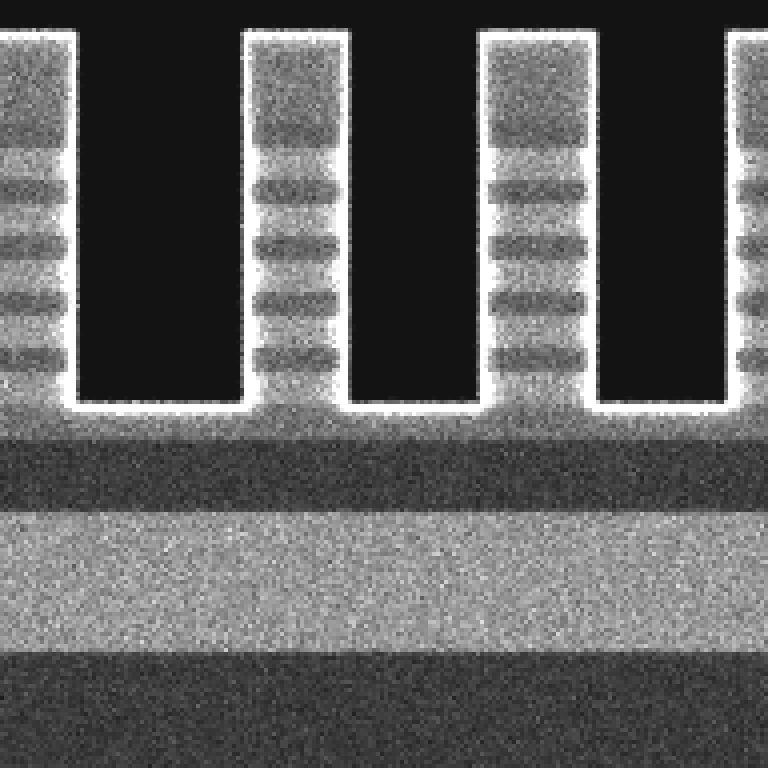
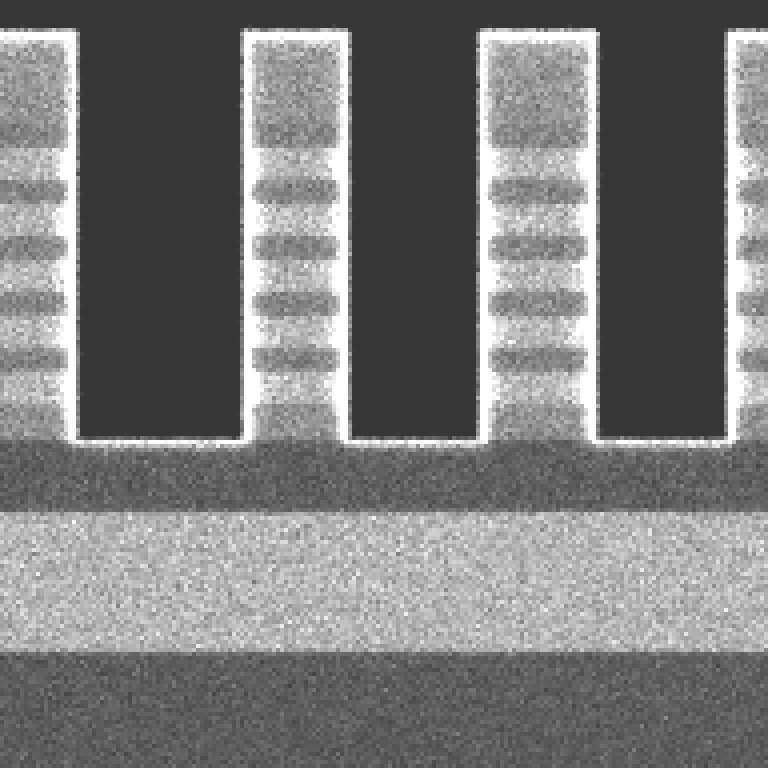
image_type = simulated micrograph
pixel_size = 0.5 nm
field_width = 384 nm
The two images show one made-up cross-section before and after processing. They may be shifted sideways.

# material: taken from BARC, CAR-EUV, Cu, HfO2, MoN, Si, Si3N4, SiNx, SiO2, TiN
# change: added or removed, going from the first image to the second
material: Si3N4
change: removed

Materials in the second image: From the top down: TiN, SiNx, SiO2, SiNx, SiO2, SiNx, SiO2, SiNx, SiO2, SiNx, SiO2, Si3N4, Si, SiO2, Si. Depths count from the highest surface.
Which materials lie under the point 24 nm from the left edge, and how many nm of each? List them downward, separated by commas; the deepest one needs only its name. TiN 46, SiNx 12, SiO2 16, SiNx 12, SiO2 16, SiNx 12, SiO2 16, SiNx 12, SiO2 16, SiNx 12, SiO2 16, Si3N4 18, Si 36, SiO2 70, Si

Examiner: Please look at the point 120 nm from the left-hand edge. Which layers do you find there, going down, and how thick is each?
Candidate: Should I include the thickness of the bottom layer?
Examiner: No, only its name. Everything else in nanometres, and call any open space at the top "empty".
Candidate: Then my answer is empty 204, Si 36, SiO2 70, Si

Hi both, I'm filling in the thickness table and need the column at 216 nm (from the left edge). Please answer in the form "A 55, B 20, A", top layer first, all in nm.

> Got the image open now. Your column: empty 204, Si 36, SiO2 70, Si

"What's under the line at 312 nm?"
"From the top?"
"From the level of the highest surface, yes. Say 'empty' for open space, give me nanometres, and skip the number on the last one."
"empty 204, Si 36, SiO2 70, Si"